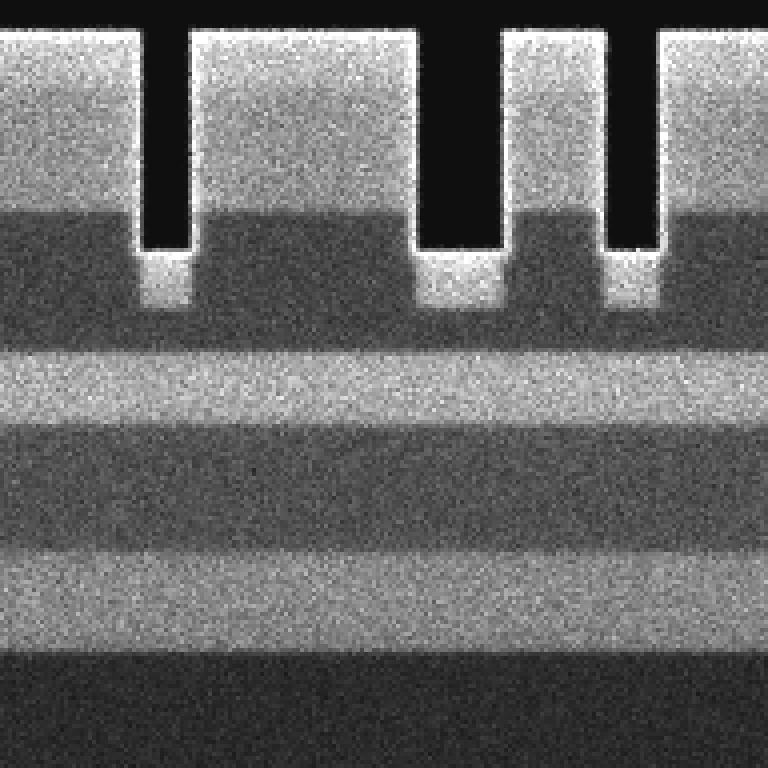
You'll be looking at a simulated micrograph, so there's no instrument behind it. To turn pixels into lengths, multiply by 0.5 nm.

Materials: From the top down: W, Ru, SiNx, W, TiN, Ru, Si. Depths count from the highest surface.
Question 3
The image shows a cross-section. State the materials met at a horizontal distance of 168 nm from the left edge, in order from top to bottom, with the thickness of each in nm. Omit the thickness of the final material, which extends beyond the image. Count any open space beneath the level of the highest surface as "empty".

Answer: W 28, Ru 62, SiNx 70, W 36, TiN 64, Ru 50, Si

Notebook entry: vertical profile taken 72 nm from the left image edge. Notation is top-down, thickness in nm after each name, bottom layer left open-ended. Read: empty 110, W 28, SiNx 22, W 36, TiN 64, Ru 50, Si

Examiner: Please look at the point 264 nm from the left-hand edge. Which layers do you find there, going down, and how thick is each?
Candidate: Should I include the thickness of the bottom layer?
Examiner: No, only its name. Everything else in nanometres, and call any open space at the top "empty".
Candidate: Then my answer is W 28, Ru 62, SiNx 70, W 36, TiN 64, Ru 50, Si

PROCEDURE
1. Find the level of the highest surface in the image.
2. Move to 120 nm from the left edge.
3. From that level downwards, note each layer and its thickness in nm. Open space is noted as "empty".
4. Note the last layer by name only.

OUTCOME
W 28, Ru 62, SiNx 70, W 36, TiN 64, Ru 50, Si